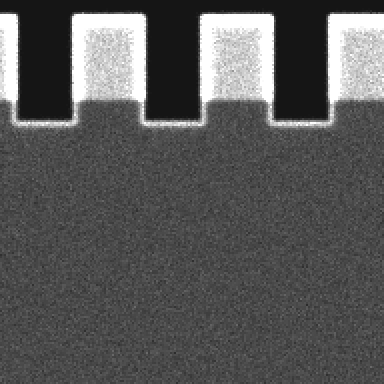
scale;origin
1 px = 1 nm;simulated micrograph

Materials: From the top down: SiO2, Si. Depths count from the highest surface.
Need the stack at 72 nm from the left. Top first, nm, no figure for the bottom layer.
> empty 106, Si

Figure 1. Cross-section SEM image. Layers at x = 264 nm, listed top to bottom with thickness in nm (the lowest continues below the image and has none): SiO2 84, Si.